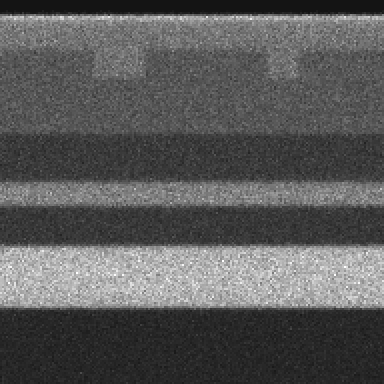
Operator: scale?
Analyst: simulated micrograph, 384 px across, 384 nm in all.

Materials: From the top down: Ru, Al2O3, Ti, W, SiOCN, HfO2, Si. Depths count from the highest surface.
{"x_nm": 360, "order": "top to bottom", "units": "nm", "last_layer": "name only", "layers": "Ru 34, Al2O3 84, Ti 48, W 24, SiOCN 40, HfO2 62, Si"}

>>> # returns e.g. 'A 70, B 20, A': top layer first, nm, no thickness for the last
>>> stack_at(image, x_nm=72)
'Ru 34, Al2O3 84, Ti 48, W 24, SiOCN 40, HfO2 62, Si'